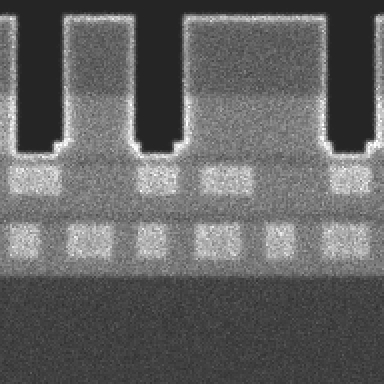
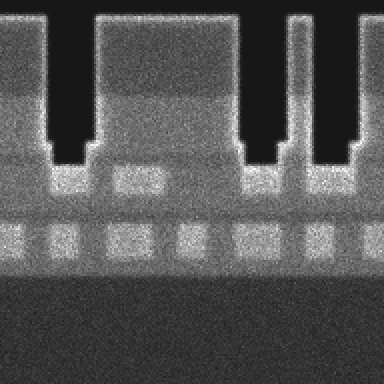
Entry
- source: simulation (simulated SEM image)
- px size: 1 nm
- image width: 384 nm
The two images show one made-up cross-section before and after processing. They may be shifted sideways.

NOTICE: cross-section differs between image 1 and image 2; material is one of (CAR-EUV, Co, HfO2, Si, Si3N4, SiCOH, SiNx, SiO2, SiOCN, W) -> removed: Si3N4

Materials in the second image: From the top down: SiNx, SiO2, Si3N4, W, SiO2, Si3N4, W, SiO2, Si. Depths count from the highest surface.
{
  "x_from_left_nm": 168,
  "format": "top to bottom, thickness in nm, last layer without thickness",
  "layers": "SiNx 80, SiO2 58, Si3N4 12, SiO2 46, Si3N4 12, SiO2 52, Si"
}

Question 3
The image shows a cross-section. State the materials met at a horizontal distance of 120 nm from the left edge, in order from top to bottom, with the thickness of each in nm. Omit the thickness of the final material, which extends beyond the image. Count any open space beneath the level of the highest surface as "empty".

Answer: SiNx 80, SiO2 58, Si3N4 12, W 28, SiO2 18, Si3N4 12, W 34, SiO2 18, Si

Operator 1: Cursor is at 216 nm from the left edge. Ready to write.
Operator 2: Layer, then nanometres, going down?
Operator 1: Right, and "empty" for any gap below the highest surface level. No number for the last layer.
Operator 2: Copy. SiNx 80, SiO2 58, Si3N4 12, SiO2 46, Si3N4 12, SiO2 52, Si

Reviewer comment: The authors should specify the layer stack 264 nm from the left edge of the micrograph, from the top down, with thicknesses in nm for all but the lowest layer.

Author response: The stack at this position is empty 150, W 28, SiO2 18, Si3N4 12, W 34, SiO2 18, Si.